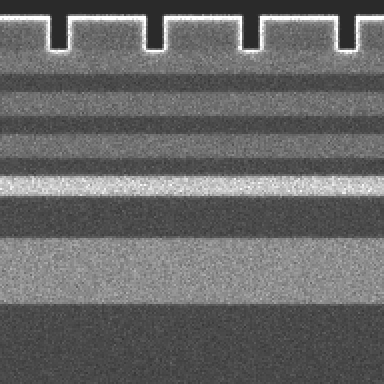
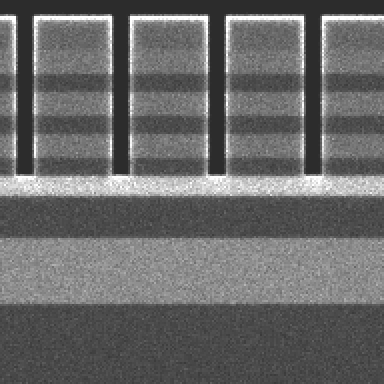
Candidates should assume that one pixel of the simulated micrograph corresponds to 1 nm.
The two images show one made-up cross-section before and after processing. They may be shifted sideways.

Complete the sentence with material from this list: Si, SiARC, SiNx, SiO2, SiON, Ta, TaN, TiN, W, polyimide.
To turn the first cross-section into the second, Si and TiN must be removed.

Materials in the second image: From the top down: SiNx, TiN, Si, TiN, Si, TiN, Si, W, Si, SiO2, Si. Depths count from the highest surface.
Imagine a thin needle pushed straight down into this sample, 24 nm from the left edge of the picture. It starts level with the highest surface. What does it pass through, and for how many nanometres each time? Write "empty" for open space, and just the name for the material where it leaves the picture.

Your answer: empty 160, W 20, Si 42, SiO2 66, Si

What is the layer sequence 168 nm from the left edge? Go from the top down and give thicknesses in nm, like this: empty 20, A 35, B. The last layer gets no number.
SiNx 34, TiN 24, Si 18, TiN 24, Si 18, TiN 24, Si 18, W 20, Si 42, SiO2 66, Si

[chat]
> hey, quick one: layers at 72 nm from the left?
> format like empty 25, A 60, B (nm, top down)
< SiNx 34, TiN 24, Si 18, TiN 24, Si 18, TiN 24, Si 18, W 20, Si 42, SiO2 66, Si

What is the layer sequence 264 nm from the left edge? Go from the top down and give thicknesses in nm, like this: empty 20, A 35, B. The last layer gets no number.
SiNx 34, TiN 24, Si 18, TiN 24, Si 18, TiN 24, Si 18, W 20, Si 42, SiO2 66, Si